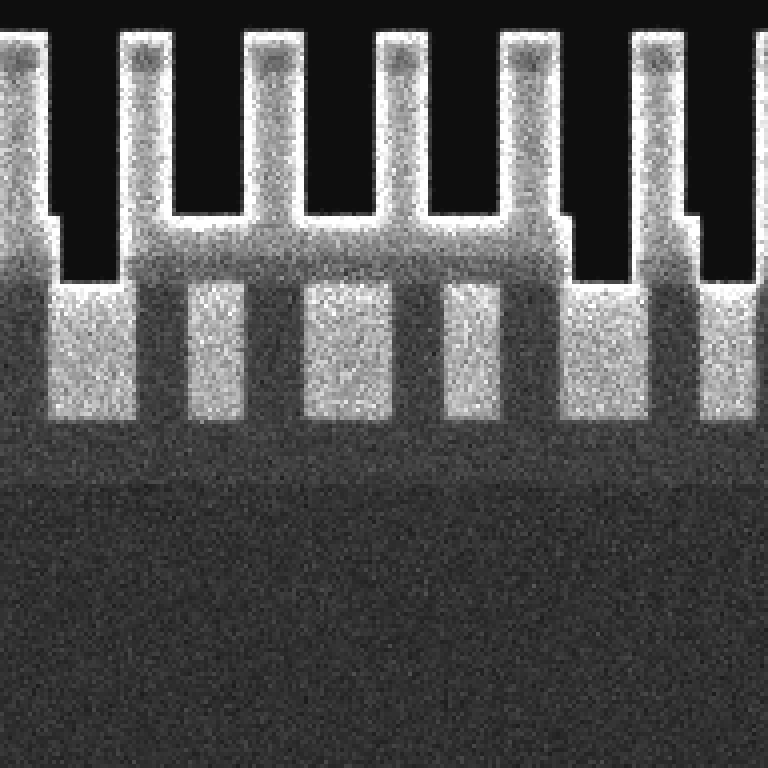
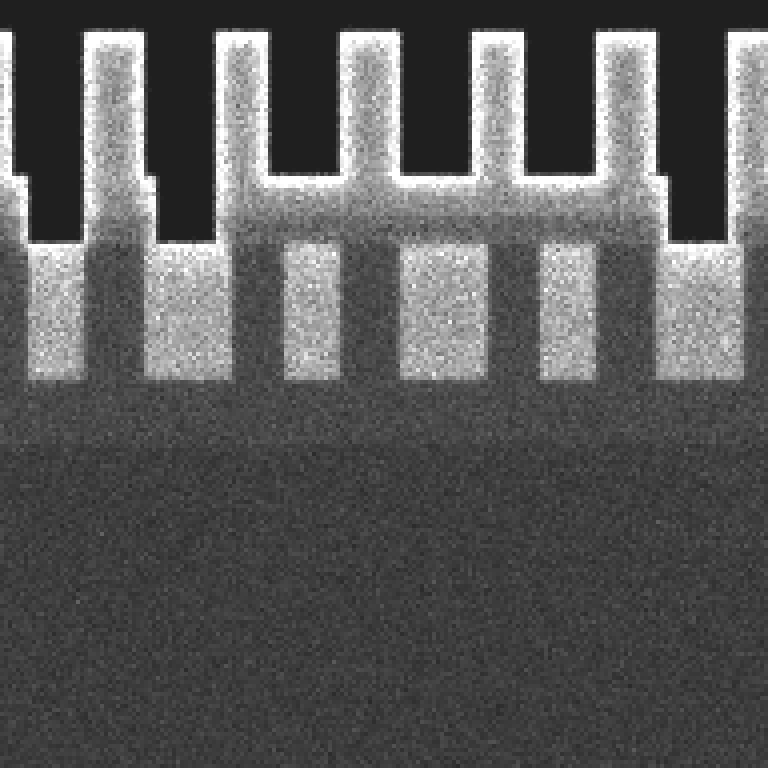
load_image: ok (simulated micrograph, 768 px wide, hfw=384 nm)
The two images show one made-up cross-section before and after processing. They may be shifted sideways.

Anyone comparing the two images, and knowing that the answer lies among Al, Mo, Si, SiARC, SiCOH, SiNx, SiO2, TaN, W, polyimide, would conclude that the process removed SiARC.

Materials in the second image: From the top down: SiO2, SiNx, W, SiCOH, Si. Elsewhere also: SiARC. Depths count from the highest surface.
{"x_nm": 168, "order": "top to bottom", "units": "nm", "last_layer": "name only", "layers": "empty 72, SiO2 20, SiNx 14, W 68, SiCOH 32, Si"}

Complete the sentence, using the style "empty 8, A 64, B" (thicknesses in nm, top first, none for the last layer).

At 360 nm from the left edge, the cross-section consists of empty 106, W 68, SiCOH 32, Si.